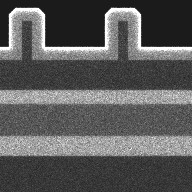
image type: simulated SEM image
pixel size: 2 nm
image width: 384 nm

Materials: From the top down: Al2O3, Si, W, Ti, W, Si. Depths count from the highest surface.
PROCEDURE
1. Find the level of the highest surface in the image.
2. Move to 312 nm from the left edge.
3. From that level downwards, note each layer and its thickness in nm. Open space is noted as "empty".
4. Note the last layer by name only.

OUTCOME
empty 78, Al2O3 26, Si 60, W 28, Ti 64, W 40, Si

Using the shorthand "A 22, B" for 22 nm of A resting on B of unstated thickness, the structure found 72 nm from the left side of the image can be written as Al2O3 104, Si 60, W 28, Ti 64, W 40, Si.